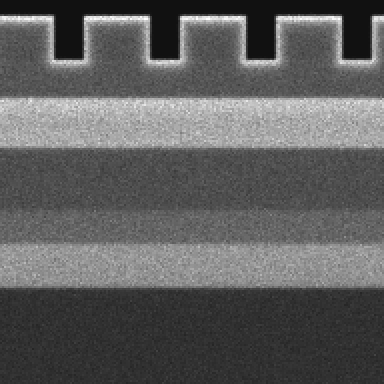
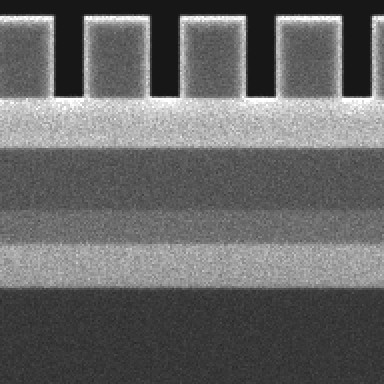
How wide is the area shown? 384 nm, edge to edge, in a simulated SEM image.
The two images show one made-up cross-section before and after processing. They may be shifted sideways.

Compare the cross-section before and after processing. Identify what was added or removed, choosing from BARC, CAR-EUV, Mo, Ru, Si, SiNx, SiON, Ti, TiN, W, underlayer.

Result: underlayer removed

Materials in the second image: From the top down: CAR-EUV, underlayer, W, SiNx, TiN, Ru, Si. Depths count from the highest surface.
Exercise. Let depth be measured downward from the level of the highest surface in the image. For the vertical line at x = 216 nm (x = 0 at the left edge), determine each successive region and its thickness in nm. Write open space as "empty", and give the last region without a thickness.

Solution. CAR-EUV 44, underlayer 38, W 50, SiNx 62, TiN 34, Ru 44, Si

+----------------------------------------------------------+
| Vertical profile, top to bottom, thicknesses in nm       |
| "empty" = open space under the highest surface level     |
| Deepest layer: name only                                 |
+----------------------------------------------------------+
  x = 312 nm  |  CAR-EUV 44, underlayer 38, W 50, SiNx 62, TiN 34, Ru 44, Si